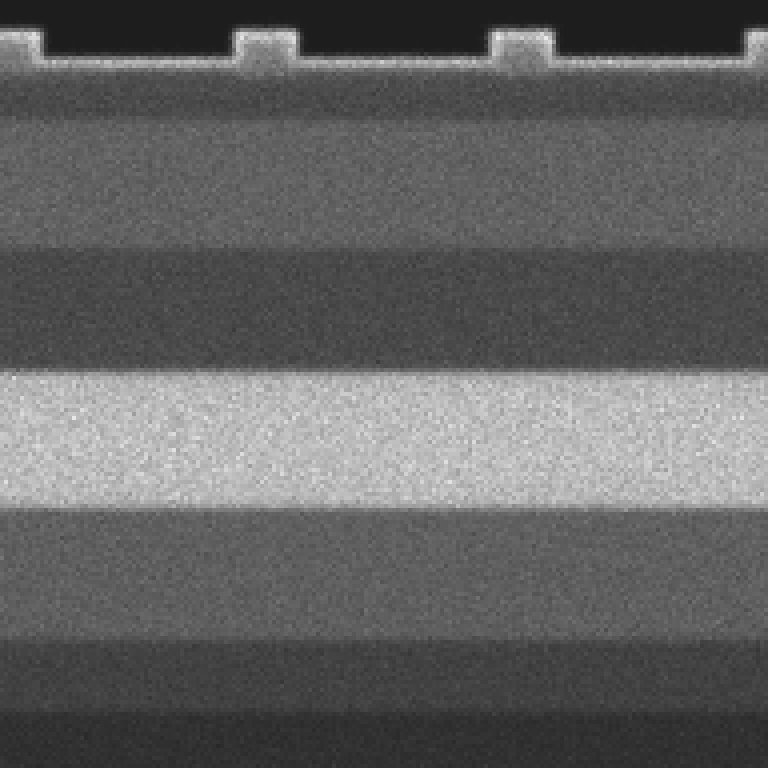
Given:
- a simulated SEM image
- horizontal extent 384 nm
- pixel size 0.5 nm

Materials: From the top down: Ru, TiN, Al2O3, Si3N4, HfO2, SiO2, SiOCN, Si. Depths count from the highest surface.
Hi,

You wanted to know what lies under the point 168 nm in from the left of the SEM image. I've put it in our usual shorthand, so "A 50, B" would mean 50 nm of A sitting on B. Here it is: empty 14, TiN 30, Al2O3 64, Si3N4 62, HfO2 68, SiO2 66, SiOCN 36, Si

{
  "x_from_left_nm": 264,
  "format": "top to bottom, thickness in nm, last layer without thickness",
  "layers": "Ru 22, TiN 22, Al2O3 64, Si3N4 62, HfO2 68, SiO2 66, SiOCN 36, Si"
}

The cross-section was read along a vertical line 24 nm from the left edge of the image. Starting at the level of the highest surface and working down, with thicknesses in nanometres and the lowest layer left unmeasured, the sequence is empty 14, TiN 30, Al2O3 64, Si3N4 62, HfO2 68, SiO2 66, SiOCN 36, Si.